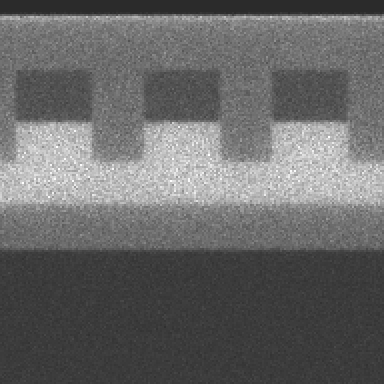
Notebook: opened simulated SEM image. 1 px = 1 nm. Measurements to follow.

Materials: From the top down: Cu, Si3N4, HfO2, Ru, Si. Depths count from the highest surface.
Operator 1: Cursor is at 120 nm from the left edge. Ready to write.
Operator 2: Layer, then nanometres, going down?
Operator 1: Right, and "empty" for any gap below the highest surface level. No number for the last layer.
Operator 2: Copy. Cu 146, HfO2 42, Ru 46, Si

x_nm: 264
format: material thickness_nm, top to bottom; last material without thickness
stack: Cu 146, HfO2 42, Ru 46, Si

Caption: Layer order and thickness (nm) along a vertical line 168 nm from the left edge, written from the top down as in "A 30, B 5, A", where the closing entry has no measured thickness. Cu 54, Si3N4 52, HfO2 82, Ru 46, Si